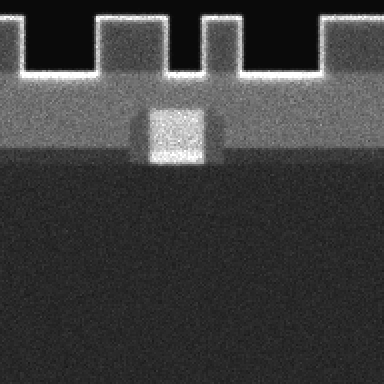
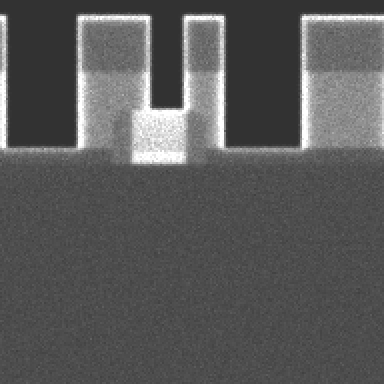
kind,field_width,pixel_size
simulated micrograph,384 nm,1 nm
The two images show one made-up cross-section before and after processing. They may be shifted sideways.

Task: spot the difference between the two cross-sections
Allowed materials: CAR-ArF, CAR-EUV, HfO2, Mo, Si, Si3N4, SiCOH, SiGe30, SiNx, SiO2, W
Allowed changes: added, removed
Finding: removed SiO2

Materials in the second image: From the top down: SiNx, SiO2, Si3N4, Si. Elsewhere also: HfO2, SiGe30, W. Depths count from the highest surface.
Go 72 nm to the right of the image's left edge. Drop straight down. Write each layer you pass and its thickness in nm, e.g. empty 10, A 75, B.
empty 132, SiGe30 16, Si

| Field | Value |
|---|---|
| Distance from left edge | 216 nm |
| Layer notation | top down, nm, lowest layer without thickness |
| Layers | SiNx 56, SiO2 76, SiGe30 16, Si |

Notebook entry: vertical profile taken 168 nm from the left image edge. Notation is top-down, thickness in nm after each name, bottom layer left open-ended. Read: empty 94, W 42, HfO2 12, Si